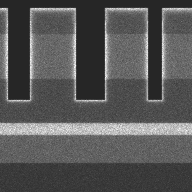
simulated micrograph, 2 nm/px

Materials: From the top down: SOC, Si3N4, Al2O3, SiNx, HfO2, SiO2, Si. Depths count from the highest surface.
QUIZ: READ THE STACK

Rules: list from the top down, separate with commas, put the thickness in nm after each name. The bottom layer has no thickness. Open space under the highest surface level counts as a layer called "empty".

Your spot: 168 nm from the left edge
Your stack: empty 184, SiNx 46, HfO2 24, SiO2 56, Si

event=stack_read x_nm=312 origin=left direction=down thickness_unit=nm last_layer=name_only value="empty 184, SiNx 46, HfO2 24, SiO2 56, Si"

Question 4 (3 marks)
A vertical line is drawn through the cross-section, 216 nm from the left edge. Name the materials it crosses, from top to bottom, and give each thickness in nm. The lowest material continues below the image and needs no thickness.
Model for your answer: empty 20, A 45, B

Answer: SOC 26, Si3N4 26, Al2O3 90, SiNx 88, HfO2 24, SiO2 56, Si